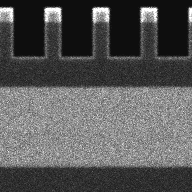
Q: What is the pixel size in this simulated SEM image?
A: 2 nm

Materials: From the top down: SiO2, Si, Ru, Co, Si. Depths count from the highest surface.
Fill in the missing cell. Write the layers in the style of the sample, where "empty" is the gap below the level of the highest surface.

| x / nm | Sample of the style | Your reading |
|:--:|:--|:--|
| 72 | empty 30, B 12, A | empty 98, Si 60, Ru 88, Co 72, Si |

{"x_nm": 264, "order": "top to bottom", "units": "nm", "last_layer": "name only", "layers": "empty 98, Si 60, Ru 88, Co 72, Si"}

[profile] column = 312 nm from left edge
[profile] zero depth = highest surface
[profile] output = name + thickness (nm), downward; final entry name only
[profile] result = SiO2 28, Si 130, Ru 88, Co 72, Si